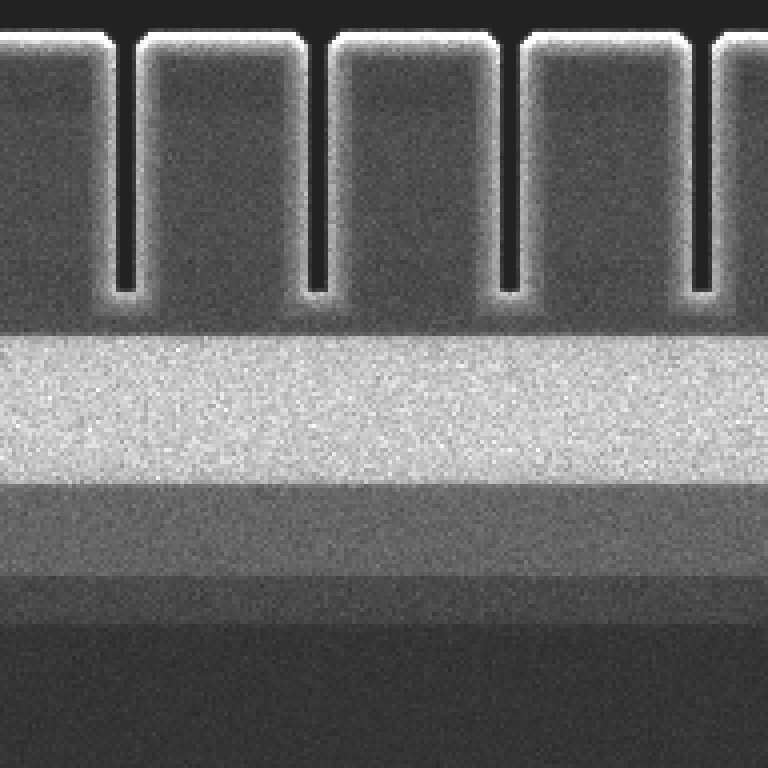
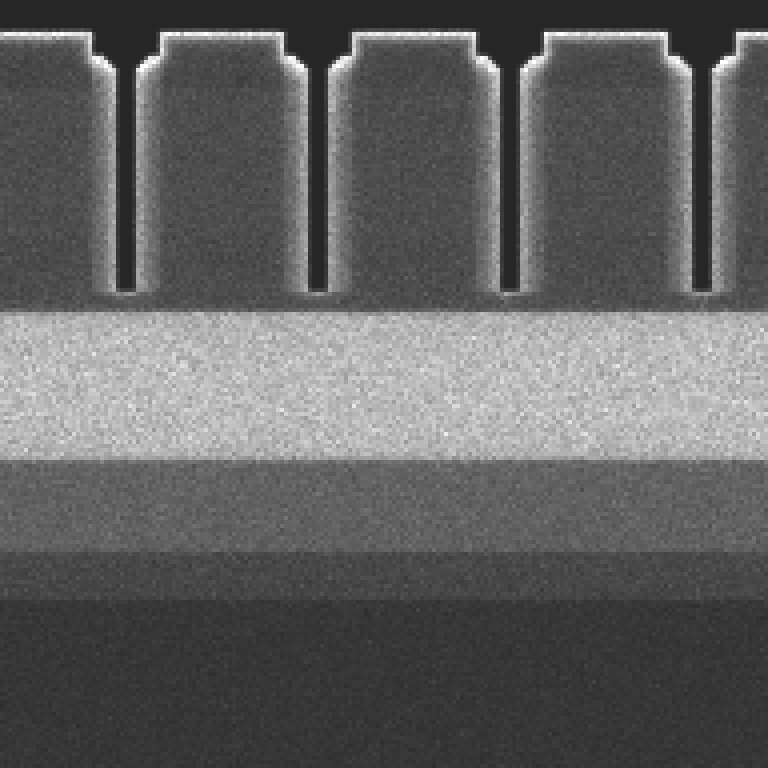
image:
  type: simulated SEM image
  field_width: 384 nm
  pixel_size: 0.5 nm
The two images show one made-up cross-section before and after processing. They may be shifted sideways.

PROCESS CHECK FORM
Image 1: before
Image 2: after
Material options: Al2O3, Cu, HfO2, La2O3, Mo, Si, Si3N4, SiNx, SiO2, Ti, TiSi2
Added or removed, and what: removed, SiO2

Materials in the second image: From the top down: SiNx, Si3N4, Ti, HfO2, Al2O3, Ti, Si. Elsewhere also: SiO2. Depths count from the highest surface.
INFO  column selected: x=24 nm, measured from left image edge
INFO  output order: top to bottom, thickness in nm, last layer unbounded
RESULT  SiNx 28, Si3N4 74, Ti 38, HfO2 74, Al2O3 46, Ti 24, Si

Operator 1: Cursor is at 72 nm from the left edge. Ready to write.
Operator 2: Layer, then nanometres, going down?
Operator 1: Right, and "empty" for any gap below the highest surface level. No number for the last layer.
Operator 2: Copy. empty 14, SiO2 116, Ti 10, HfO2 74, Al2O3 46, Ti 24, Si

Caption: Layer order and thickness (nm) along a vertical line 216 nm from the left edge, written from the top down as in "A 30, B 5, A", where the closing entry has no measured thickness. SiNx 28, Si3N4 74, Ti 38, HfO2 74, Al2O3 46, Ti 24, Si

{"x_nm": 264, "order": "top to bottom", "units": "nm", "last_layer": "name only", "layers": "empty 14, SiO2 116, Ti 10, HfO2 74, Al2O3 46, Ti 24, Si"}